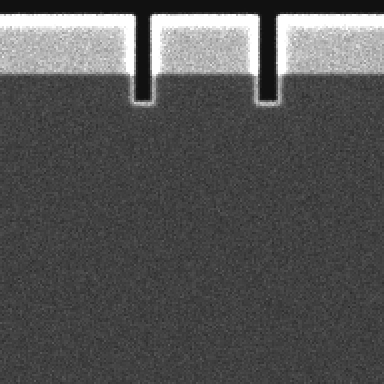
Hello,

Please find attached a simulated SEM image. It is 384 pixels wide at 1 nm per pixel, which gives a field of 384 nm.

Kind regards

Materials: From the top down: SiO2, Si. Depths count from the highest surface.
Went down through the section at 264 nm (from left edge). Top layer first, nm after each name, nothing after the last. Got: empty 86, Si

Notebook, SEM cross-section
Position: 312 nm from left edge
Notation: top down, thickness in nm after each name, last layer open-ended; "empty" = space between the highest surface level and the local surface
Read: SiO2 58, Si